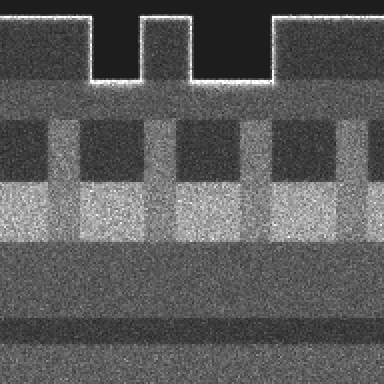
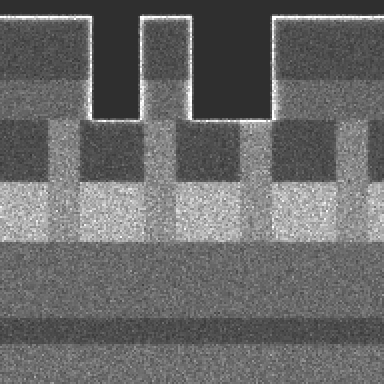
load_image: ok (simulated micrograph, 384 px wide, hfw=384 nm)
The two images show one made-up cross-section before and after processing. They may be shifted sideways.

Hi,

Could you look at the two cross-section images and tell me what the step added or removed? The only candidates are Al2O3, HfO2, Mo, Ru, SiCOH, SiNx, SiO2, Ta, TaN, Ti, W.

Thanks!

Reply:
removed SiO2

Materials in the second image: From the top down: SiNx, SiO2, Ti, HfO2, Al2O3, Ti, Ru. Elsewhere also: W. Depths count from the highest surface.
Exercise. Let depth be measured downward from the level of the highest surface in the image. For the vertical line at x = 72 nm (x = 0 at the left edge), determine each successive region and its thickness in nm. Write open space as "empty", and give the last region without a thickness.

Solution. SiNx 64, SiO2 40, W 122, Al2O3 76, Ti 26, Ru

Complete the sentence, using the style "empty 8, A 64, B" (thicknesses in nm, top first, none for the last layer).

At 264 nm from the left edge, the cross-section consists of empty 104, W 122, Al2O3 76, Ti 26, Ru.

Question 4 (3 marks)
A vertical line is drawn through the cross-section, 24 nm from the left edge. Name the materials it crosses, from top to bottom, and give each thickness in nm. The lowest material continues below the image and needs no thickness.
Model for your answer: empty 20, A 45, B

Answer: SiNx 64, SiO2 40, Ti 62, HfO2 60, Al2O3 76, Ti 26, Ru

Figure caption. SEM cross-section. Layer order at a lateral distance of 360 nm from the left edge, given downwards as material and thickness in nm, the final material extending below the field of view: SiNx 64, SiO2 40, W 122, Al2O3 76, Ti 26, Ru